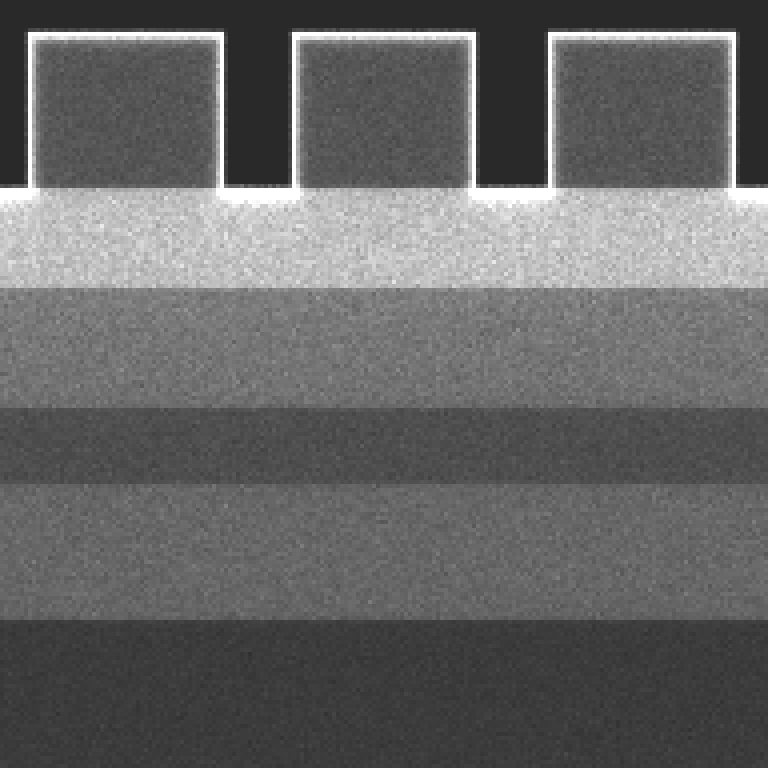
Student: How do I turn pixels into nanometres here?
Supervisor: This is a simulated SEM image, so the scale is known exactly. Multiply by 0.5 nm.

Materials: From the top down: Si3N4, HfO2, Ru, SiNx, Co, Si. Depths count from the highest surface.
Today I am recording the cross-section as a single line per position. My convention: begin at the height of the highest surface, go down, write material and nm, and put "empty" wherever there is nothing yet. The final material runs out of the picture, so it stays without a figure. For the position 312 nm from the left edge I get Si3N4 78, HfO2 50, Ru 60, SiNx 38, Co 68, Si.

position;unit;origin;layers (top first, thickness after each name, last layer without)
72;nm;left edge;Si3N4 78, HfO2 50, Ru 60, SiNx 38, Co 68, Si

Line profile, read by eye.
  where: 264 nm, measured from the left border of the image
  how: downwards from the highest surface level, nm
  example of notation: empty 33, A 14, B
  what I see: empty 78, HfO2 50, Ru 60, SiNx 38, Co 68, Si